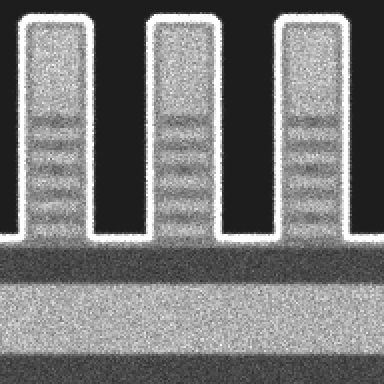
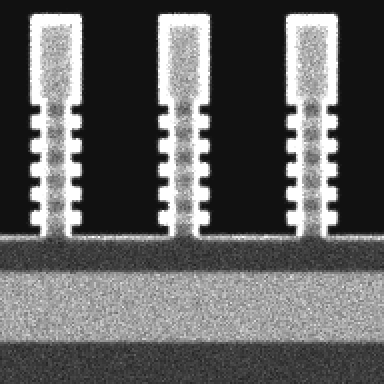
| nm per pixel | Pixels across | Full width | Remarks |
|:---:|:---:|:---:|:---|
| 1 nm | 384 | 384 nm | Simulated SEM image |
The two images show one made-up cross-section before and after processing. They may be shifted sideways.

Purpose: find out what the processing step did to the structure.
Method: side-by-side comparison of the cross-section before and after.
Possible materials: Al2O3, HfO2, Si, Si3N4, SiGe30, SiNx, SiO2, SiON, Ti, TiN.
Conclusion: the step removed Si3N4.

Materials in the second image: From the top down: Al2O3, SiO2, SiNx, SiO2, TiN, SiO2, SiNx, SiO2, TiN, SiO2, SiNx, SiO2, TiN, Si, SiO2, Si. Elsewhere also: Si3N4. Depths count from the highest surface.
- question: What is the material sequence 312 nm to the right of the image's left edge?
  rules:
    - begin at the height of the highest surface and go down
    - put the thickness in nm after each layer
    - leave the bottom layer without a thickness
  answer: Al2O3 60, SiO2 28, SiNx 12, SiO2 12, TiN 12, SiO2 12, SiNx 12, SiO2 12, TiN 12, SiO2 12, SiNx 12, SiO2 12, TiN 12, Si 36, SiO2 70, Si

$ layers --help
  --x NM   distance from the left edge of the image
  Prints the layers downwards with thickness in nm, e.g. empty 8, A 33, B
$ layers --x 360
empty 220, Si 36, SiO2 70, Si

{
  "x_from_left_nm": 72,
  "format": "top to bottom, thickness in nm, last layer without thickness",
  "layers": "Al2O3 60, SiO2 28, empty 12, SiO2 12, empty 12, SiO2 12, empty 12, SiO2 12, empty 12, SiO2 12, empty 12, SiO2 12, empty 12, Si 36, SiO2 70, Si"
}